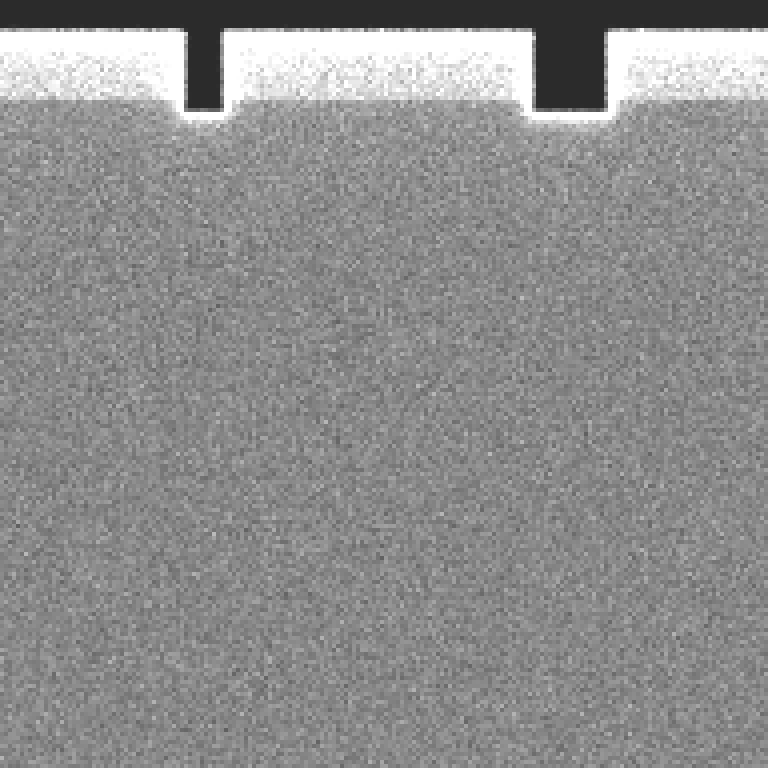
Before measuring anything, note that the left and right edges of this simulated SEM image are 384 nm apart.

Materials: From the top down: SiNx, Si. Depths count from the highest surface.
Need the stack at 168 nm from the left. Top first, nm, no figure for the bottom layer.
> SiNx 34, Si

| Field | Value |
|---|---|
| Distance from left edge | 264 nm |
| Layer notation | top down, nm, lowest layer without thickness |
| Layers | SiNx 34, Si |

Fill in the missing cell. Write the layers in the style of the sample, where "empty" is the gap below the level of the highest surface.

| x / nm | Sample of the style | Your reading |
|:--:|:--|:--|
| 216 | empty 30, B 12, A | SiNx 34, Si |